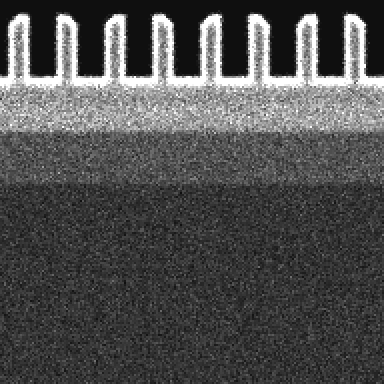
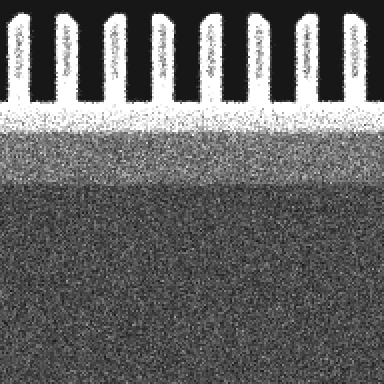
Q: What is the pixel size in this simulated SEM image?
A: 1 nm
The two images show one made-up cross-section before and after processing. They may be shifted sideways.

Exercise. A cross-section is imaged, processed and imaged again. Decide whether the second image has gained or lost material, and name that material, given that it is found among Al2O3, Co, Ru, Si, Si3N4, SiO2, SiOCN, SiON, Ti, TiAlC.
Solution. removed: SiO2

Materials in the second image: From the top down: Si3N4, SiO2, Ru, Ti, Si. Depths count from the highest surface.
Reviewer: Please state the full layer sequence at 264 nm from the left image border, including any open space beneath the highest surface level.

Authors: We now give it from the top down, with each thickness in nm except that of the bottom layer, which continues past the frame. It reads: empty 6, Si3N4 56, SiO2 26, Ru 28, Ti 52, Si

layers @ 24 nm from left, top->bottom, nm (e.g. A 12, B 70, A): Si3N4 62, SiO2 26, Ru 28, Ti 52, Si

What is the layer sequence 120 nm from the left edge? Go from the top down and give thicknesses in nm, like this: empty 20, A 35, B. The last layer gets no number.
Si3N4 62, SiO2 26, Ru 28, Ti 52, Si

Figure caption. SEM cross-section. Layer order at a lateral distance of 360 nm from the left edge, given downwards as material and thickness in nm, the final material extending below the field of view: empty 6, Si3N4 56, SiO2 26, Ru 28, Ti 52, Si